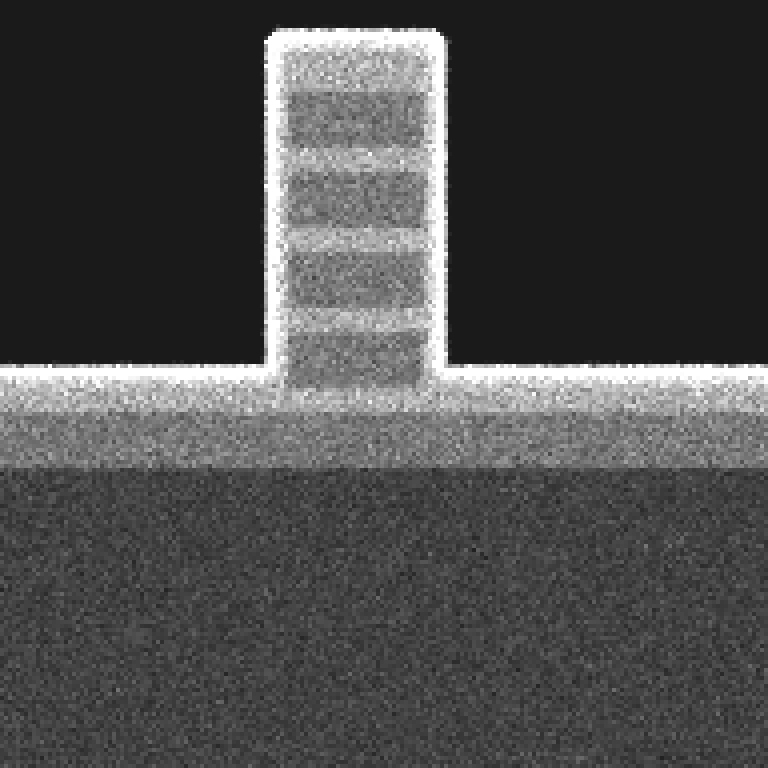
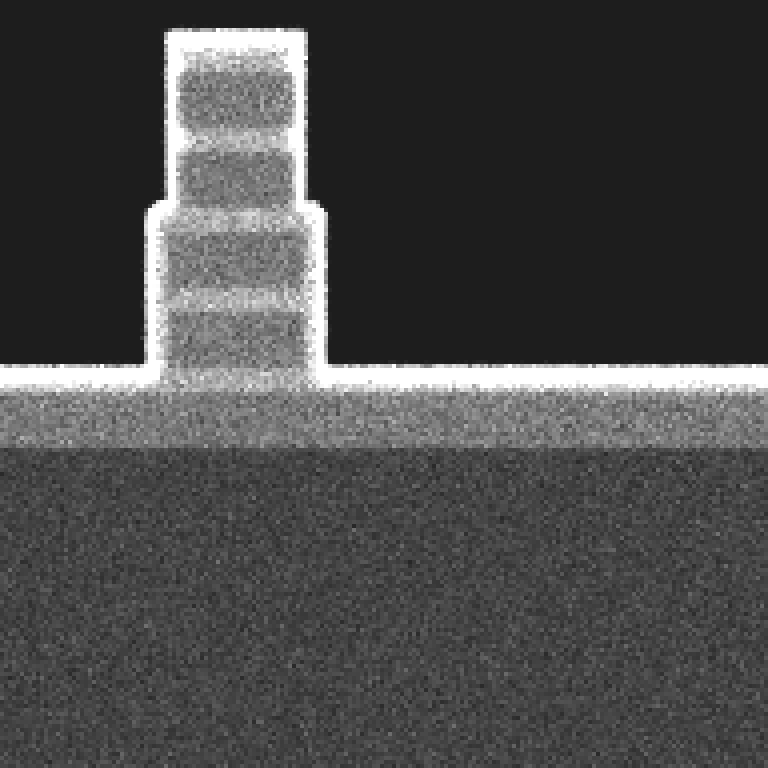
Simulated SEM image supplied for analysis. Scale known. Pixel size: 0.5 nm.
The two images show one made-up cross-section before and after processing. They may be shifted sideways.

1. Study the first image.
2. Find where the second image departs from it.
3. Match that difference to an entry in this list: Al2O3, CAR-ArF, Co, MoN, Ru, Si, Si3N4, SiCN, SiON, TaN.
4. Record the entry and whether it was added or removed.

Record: Ru / removed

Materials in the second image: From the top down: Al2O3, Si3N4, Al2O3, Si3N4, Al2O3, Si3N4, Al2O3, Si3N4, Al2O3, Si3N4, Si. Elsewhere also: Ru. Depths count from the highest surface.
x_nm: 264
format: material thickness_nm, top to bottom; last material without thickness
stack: empty 168, Al2O3 12, Si3N4 28, Si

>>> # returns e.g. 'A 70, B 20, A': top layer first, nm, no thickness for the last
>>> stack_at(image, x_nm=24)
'empty 168, Al2O3 12, Si3N4 28, Si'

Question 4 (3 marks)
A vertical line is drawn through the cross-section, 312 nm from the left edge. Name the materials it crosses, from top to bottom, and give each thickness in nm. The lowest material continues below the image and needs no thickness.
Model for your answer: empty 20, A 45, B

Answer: empty 168, Al2O3 12, Si3N4 28, Si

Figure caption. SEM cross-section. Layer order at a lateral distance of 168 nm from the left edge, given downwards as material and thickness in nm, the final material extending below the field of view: empty 168, Al2O3 12, Si3N4 28, Si